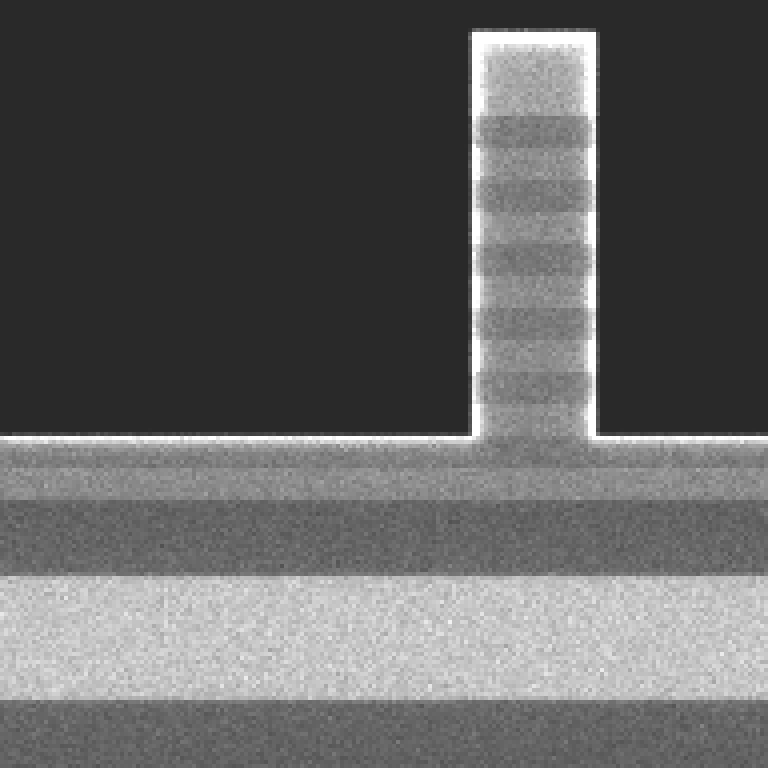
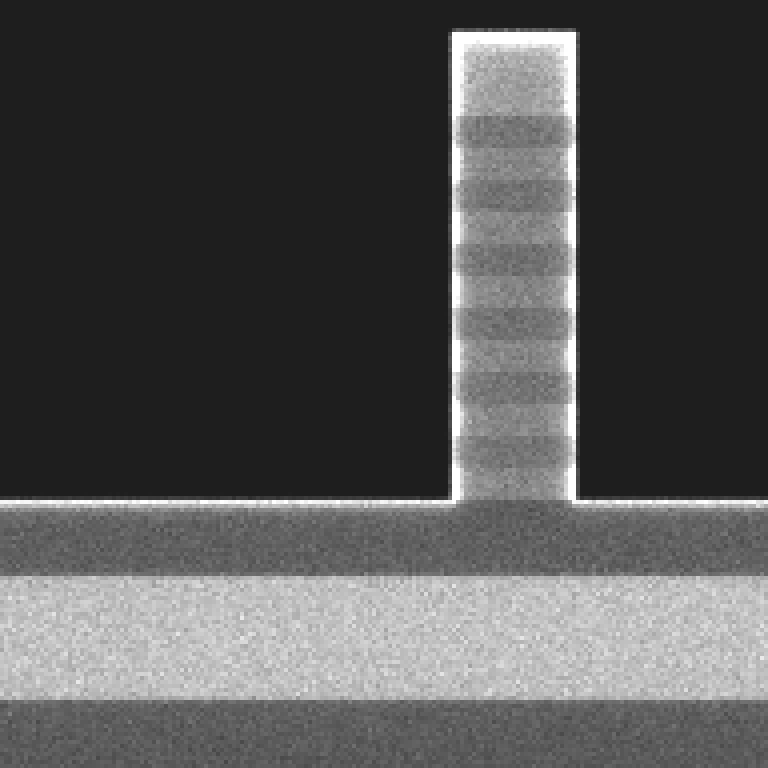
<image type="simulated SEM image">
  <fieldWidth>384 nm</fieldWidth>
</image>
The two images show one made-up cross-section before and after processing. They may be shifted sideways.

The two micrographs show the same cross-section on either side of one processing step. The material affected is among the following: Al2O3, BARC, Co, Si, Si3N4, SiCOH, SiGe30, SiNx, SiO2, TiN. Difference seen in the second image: SiGe30 and SiNx removed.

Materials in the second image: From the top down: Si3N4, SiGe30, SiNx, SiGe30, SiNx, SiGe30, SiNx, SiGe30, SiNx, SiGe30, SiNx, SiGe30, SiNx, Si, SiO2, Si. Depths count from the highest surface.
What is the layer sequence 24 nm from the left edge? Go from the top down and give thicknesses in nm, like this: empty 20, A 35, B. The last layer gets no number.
empty 234, Si 38, SiO2 62, Si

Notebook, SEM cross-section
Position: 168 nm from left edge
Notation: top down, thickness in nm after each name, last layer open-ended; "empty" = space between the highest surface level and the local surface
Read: empty 234, Si 38, SiO2 62, Si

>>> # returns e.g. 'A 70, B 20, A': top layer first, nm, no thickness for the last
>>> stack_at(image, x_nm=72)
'empty 234, Si 38, SiO2 62, Si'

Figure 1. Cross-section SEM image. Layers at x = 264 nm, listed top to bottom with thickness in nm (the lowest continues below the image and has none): Si3N4 42, SiGe30 16, SiNx 16, SiGe30 16, SiNx 16, SiGe30 16, SiNx 16, SiGe30 16, SiNx 16, SiGe30 16, SiNx 16, SiGe30 16, SiNx 16, Si 38, SiO2 62, Si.